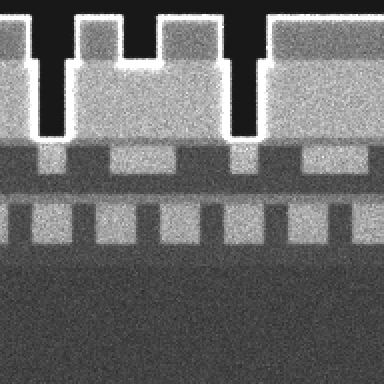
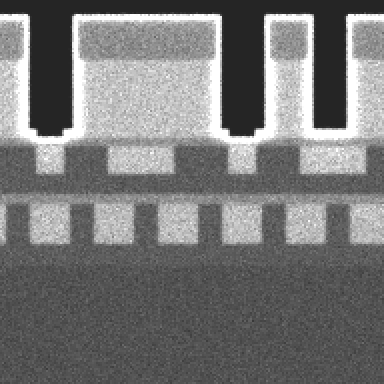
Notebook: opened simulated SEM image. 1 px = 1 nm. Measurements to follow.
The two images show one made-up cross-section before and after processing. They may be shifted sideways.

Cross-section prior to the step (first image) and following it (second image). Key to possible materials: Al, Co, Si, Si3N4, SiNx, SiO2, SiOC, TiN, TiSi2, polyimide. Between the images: SiO2 was removed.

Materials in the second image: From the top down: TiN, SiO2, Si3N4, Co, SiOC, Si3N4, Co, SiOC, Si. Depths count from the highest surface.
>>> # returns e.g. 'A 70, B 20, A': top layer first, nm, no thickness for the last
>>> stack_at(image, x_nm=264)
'empty 114, SiO2 8, Si3N4 8, SiOC 48, Si3N4 10, SiOC 62, Si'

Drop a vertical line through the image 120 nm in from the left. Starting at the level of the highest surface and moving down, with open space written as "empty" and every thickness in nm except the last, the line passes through TiN 44, SiO2 78, Si3N4 8, Co 28, SiOC 20, Si3N4 10, Co 40, SiOC 22, Si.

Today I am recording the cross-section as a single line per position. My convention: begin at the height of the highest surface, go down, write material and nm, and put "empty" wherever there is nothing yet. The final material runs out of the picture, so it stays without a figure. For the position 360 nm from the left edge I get TiN 44, SiO2 78, Si3N4 8, Co 28, SiOC 20, Si3N4 10, Co 40, SiOC 22, Si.